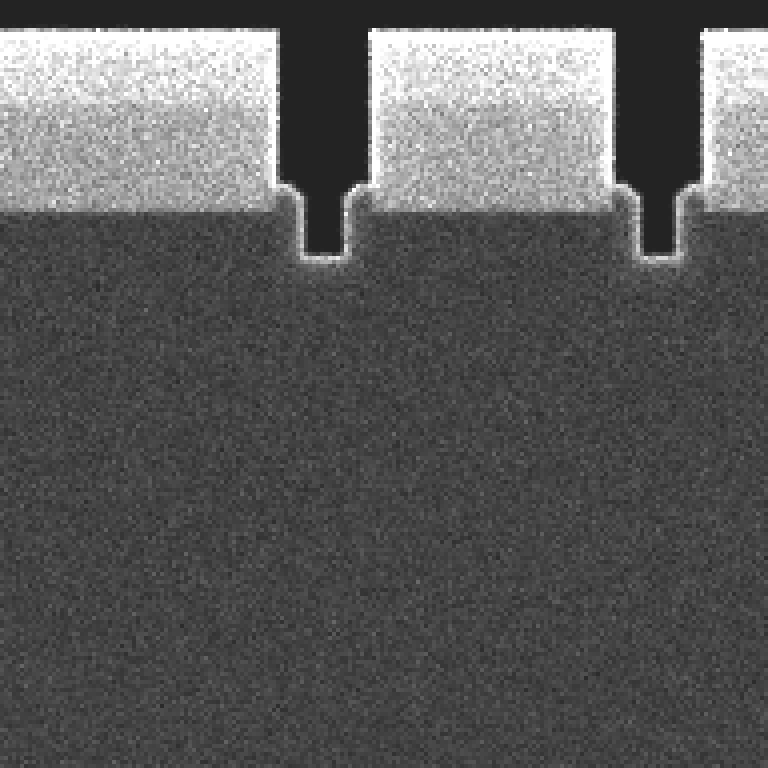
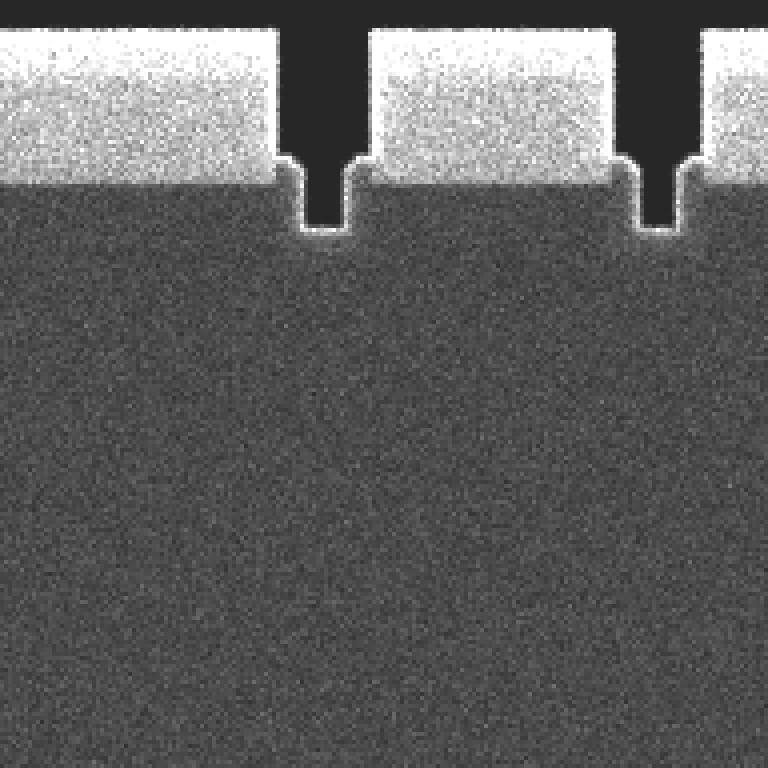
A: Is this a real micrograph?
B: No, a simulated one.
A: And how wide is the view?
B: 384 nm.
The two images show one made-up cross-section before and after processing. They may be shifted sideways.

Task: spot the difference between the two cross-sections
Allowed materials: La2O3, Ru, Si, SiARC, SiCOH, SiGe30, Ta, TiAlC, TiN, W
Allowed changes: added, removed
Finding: removed W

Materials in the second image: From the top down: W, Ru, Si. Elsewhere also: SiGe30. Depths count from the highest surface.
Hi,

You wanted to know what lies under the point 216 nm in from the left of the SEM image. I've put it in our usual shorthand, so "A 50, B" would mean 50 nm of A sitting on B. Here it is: W 22, Ru 54, Si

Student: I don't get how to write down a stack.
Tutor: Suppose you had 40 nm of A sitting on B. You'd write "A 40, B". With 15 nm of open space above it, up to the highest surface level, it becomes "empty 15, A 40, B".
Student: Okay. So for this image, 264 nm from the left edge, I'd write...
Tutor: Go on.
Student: W 22, Ru 54, Si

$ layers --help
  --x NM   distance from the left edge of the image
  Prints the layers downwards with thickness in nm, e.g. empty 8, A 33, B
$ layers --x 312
empty 62, SiGe30 50, Si